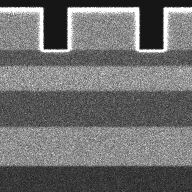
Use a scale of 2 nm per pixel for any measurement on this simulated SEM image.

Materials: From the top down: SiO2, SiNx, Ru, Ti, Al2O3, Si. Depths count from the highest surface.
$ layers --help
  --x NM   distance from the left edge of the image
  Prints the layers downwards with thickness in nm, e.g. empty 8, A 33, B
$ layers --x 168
SiO2 84, SiNx 32, Ru 50, Ti 72, Al2O3 78, Si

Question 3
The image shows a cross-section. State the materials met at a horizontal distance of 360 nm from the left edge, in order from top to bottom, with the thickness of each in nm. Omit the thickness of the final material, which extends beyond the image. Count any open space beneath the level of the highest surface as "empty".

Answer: SiO2 84, SiNx 32, Ru 50, Ti 72, Al2O3 78, Si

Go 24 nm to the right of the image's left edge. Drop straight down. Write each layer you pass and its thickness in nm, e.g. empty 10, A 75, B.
SiO2 84, SiNx 32, Ru 50, Ti 72, Al2O3 78, Si